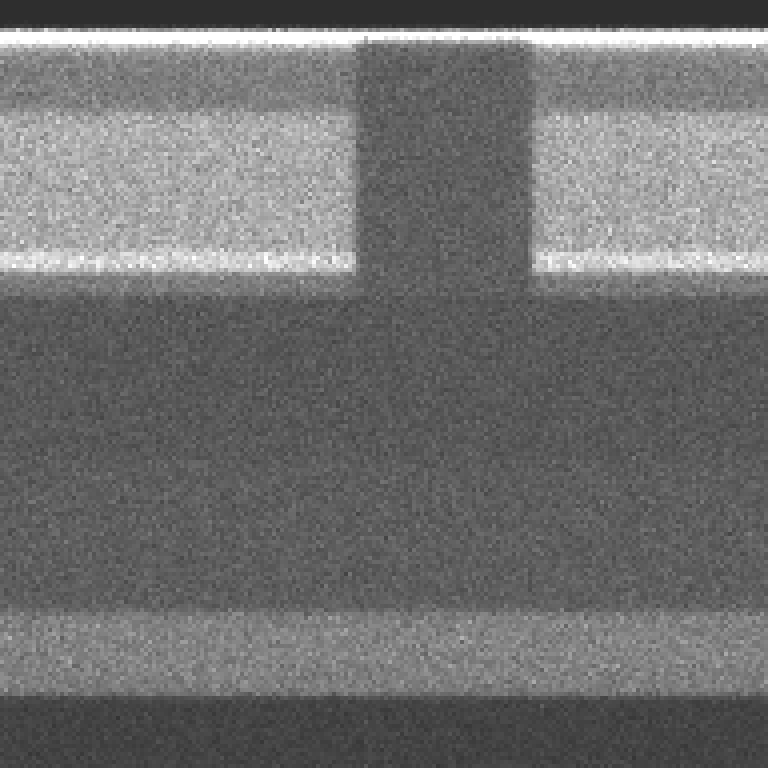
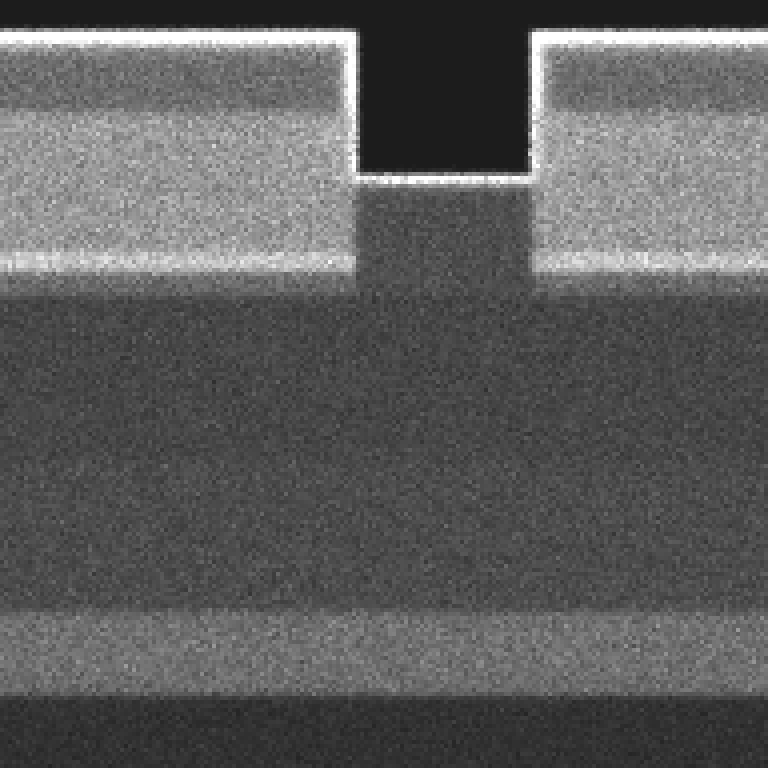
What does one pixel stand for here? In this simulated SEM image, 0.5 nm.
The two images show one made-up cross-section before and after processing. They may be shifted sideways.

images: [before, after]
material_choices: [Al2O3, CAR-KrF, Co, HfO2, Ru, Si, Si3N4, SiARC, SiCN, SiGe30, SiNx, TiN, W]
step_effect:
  removed: Si3N4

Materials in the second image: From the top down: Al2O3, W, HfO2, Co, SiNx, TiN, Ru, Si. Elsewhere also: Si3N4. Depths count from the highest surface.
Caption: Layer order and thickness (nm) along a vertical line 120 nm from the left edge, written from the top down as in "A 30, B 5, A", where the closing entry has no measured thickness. Al2O3 40, W 70, HfO2 10, Co 12, SiNx 82, TiN 76, Ru 42, Si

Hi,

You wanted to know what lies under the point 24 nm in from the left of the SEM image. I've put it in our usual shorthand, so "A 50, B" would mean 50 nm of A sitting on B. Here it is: Al2O3 40, W 70, HfO2 10, Co 12, SiNx 82, TiN 76, Ru 42, Si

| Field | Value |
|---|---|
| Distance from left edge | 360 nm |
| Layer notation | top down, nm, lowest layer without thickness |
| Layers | Al2O3 40, W 70, HfO2 10, Co 12, SiNx 82, TiN 76, Ru 42, Si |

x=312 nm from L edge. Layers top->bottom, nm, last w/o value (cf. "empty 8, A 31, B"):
Al2O3 40, W 70, HfO2 10, Co 12, SiNx 82, TiN 76, Ru 42, Si